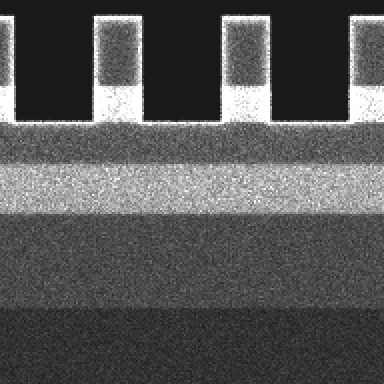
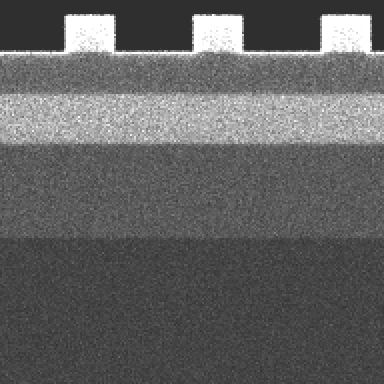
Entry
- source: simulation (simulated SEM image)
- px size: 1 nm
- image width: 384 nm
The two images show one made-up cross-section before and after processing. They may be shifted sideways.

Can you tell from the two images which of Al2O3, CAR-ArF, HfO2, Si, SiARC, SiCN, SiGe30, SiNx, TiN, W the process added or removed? Yes, it removed SiARC.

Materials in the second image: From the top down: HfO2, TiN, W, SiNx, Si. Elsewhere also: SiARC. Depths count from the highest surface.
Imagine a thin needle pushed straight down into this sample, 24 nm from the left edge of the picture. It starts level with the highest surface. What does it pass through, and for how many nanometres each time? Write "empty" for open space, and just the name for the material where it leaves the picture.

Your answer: empty 36, TiN 42, W 50, SiNx 94, Si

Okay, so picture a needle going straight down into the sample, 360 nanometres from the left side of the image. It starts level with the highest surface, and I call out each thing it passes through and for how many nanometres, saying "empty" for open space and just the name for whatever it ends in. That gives HfO2 36, TiN 42, W 50, SiNx 94, Si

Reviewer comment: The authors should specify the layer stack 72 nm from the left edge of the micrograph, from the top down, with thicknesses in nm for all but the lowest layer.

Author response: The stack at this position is HfO2 36, TiN 42, W 50, SiNx 94, Si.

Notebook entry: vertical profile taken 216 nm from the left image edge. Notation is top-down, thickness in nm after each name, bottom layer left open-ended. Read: HfO2 36, TiN 42, W 50, SiNx 94, Si